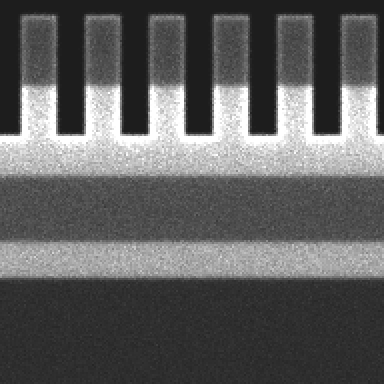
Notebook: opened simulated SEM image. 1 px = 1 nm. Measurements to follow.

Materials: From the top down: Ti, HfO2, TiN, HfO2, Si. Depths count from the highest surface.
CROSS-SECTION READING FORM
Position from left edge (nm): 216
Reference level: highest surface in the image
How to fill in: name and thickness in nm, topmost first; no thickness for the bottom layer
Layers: Ti 70, HfO2 90, TiN 66, HfO2 36, Si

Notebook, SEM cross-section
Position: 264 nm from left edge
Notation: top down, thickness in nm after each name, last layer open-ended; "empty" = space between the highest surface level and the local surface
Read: empty 120, HfO2 40, TiN 66, HfO2 36, Si